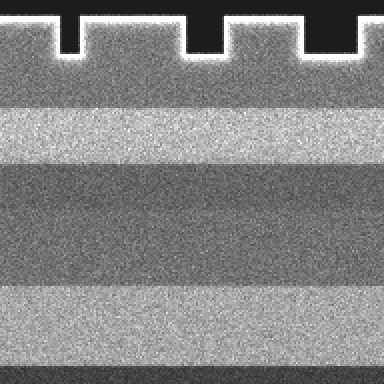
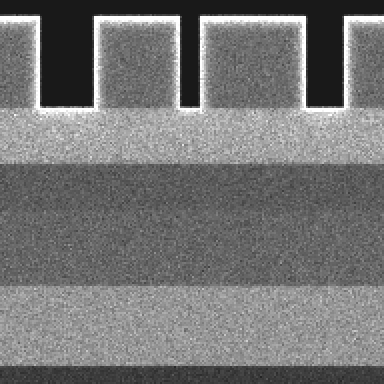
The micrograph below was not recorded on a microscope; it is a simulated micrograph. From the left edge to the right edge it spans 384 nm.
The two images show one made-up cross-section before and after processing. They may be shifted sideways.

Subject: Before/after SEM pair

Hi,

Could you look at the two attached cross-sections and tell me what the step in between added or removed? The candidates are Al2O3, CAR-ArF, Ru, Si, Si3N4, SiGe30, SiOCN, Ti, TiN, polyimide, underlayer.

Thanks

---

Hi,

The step removed underlayer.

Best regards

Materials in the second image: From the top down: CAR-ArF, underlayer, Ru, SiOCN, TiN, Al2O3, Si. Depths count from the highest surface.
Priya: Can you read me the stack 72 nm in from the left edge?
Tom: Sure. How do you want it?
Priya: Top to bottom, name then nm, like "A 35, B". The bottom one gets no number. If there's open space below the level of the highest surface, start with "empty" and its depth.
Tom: empty 92, Ru 56, SiOCN 46, TiN 76, Al2O3 80, Si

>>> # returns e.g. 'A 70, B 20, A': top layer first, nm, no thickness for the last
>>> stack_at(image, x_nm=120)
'CAR-ArF 38, underlayer 54, Ru 56, SiOCN 46, TiN 76, Al2O3 80, Si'